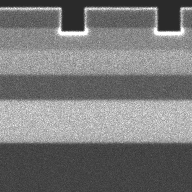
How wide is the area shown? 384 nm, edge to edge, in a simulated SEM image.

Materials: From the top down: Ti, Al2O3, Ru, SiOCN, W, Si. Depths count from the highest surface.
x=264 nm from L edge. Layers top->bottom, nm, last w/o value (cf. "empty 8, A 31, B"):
Ti 40, Al2O3 44, Ru 50, SiOCN 50, W 86, Si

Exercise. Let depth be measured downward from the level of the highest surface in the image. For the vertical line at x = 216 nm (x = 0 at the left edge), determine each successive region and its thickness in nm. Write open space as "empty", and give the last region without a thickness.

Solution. Ti 40, Al2O3 44, Ru 50, SiOCN 50, W 86, Si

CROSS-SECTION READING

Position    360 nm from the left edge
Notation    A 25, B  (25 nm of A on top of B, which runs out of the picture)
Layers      empty 48, Al2O3 36, Ru 50, SiOCN 50, W 86, Si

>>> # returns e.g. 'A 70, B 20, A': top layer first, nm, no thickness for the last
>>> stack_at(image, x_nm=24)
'Ti 40, Al2O3 44, Ru 50, SiOCN 50, W 86, Si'